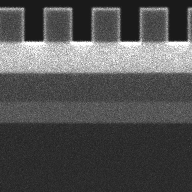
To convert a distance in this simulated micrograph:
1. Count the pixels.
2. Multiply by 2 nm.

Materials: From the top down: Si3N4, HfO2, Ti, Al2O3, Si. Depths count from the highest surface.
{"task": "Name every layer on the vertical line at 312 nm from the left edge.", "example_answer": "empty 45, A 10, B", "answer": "Si3N4 68, HfO2 62, Ti 58, Al2O3 42, Si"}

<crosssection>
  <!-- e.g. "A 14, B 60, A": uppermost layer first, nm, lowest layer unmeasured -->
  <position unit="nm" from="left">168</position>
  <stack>empty 68, HfO2 62, Ti 58, Al2O3 42, Si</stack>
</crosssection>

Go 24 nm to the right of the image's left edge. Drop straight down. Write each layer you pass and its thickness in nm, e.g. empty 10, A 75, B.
Si3N4 68, HfO2 62, Ti 58, Al2O3 42, Si